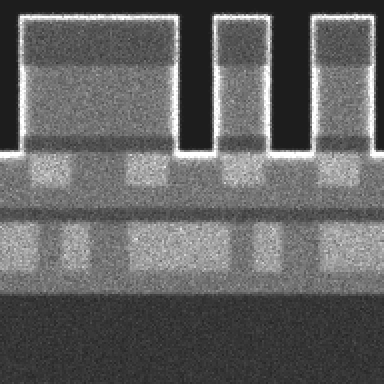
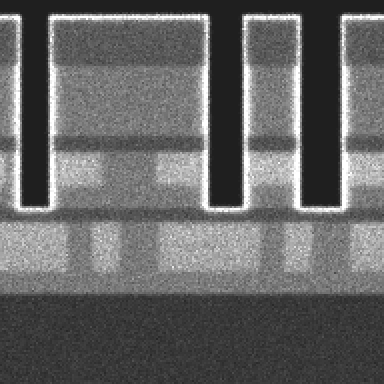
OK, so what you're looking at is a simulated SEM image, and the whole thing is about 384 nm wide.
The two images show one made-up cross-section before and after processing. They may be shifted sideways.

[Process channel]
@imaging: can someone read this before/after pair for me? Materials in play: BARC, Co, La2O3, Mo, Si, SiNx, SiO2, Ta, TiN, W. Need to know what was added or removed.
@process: SiO2 removed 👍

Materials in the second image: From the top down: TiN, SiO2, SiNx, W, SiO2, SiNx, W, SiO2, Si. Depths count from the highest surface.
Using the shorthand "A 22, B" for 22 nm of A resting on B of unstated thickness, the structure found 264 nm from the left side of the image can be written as TiN 50, SiO2 70, SiNx 16, W 34, SiO2 22, SiNx 14, SiO2 72, Si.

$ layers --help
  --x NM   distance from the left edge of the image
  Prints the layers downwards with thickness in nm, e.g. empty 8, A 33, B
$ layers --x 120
TiN 50, SiO2 70, SiNx 16, SiO2 56, SiNx 14, SiO2 72, Si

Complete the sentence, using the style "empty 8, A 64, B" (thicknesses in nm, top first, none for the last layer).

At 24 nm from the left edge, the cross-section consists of empty 192, SiNx 14, W 50, SiO2 22, Si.